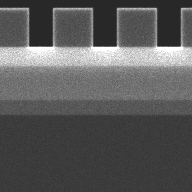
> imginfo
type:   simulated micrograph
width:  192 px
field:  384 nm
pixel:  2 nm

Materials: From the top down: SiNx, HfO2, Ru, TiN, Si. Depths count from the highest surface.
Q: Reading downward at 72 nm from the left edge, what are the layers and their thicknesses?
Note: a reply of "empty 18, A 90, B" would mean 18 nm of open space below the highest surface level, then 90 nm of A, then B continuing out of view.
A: empty 78, HfO2 38, Ru 68, TiN 30, Si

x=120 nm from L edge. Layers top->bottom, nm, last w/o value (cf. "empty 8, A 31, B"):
SiNx 78, HfO2 38, Ru 68, TiN 30, Si